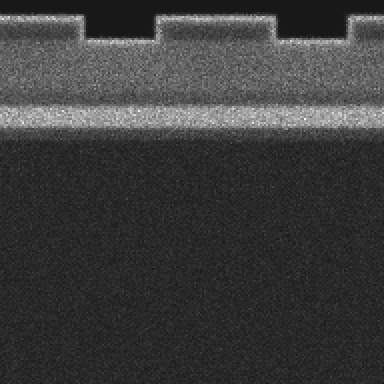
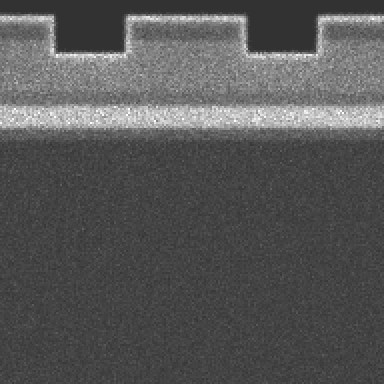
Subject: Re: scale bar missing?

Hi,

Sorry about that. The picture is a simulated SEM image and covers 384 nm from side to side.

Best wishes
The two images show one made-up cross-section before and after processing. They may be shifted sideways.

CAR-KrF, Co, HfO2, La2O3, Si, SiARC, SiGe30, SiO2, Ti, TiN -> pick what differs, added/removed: Co removed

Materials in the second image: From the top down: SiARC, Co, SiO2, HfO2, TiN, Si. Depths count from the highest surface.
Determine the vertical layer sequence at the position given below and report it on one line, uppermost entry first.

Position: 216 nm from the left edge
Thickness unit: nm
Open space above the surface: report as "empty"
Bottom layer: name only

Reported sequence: SiARC 24, Co 52, SiO2 14, HfO2 22, TiN 12, Si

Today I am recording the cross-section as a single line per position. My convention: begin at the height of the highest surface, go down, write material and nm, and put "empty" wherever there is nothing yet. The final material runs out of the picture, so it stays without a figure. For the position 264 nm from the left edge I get empty 38, Co 38, SiO2 14, HfO2 22, TiN 12, Si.